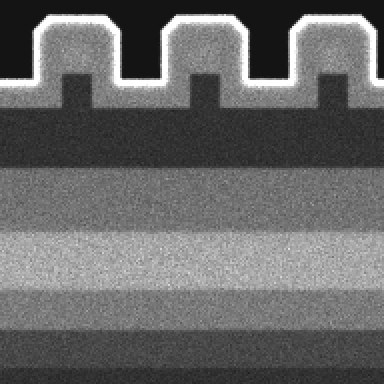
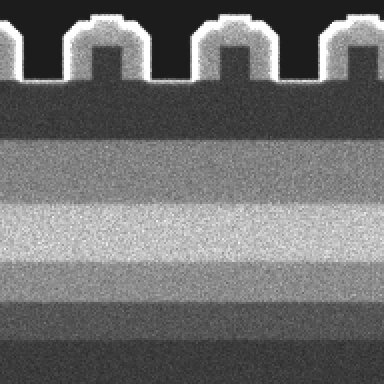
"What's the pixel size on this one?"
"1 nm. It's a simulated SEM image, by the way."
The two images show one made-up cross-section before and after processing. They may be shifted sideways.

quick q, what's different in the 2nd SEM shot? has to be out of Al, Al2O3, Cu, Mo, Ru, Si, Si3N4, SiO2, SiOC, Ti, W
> Al2O3 removed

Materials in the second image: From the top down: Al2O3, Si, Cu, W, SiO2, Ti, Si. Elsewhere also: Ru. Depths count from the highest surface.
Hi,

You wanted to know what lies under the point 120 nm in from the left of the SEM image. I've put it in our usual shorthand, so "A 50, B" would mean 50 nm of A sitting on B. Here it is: Ru 30, Si 94, Cu 64, W 58, SiO2 40, Ti 38, Si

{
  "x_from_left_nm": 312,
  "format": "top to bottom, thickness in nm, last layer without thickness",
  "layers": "empty 64, Si 60, Cu 64, W 58, SiO2 40, Ti 38, Si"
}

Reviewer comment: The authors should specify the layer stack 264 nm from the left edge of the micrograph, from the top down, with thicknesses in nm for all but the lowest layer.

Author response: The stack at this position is empty 8, Al2O3 56, Si 60, Cu 64, W 58, SiO2 40, Ti 38, Si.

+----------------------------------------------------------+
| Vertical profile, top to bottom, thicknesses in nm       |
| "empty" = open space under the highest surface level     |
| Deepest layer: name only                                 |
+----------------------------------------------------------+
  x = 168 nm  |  empty 64, Si 60, Cu 64, W 58, SiO2 40, Ti 38, Si